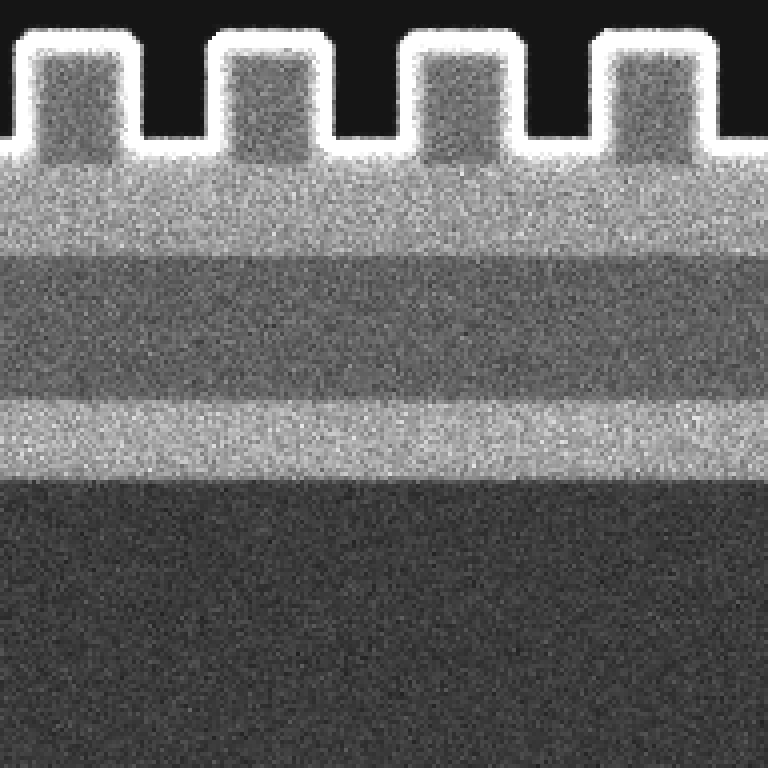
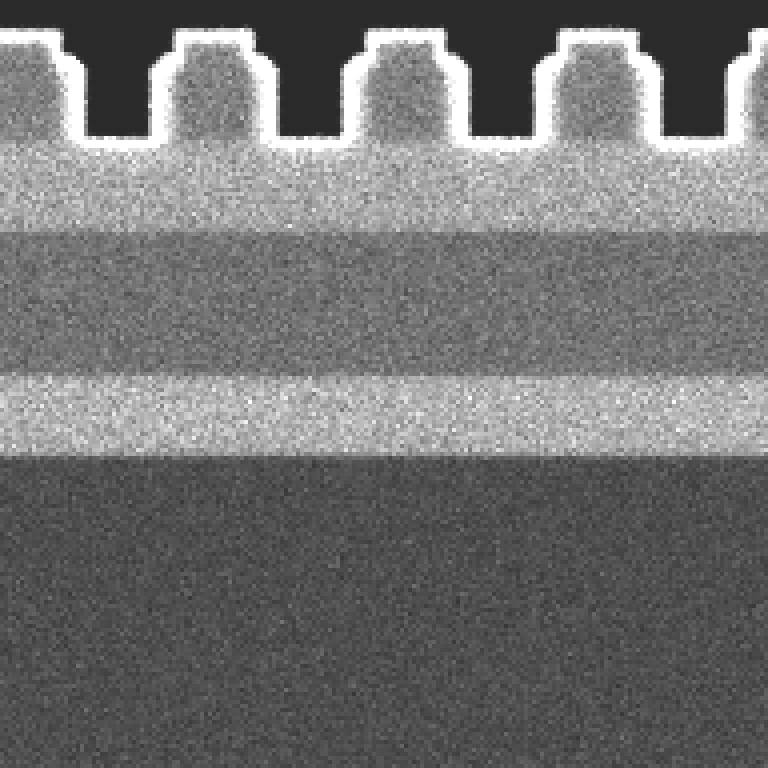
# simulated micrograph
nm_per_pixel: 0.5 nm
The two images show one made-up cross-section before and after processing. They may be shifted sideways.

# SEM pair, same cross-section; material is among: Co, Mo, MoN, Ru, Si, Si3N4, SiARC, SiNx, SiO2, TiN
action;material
removed;SiO2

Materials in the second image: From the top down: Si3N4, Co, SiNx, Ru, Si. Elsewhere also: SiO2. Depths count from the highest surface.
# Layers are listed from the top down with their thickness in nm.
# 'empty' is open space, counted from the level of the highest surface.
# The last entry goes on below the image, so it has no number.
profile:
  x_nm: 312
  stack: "Si3N4 54, Co 46, SiNx 72, Ru 40, Si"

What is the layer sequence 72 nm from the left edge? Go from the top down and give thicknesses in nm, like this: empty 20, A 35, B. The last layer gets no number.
empty 54, Co 46, SiNx 72, Ru 40, Si